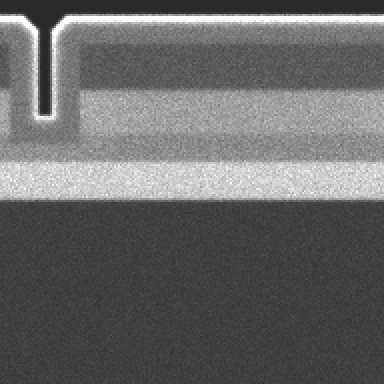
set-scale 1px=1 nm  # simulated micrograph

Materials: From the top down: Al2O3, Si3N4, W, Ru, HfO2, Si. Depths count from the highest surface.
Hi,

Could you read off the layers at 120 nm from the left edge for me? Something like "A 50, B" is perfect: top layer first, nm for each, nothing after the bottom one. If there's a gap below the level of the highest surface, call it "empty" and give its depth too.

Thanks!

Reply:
Al2O3 28, Si3N4 46, W 44, Ru 28, HfO2 38, Si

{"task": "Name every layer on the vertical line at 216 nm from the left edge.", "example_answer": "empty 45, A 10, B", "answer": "Al2O3 28, Si3N4 46, W 44, Ru 28, HfO2 38, Si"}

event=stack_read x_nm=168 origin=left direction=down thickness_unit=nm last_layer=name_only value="Al2O3 28, Si3N4 46, W 44, Ru 28, HfO2 38, Si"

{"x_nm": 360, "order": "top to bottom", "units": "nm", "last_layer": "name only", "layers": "Al2O3 28, Si3N4 46, W 44, Ru 28, HfO2 38, Si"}